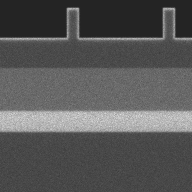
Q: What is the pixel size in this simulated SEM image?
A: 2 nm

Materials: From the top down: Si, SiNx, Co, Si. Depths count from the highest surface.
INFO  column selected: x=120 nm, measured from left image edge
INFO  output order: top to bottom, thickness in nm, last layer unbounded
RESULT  empty 60, Si 60, SiNx 86, Co 42, Si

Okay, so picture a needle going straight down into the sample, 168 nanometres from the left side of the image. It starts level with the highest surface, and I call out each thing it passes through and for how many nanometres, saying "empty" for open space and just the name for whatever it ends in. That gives empty 60, Si 60, SiNx 86, Co 42, Si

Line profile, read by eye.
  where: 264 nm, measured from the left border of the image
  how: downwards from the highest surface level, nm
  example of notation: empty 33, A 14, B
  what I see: empty 60, Si 60, SiNx 86, Co 42, Si